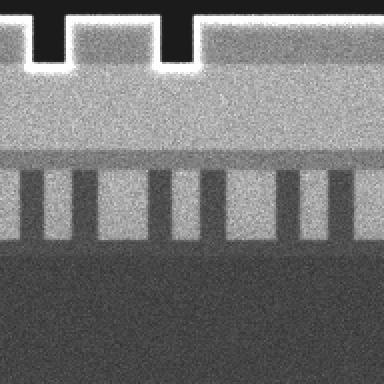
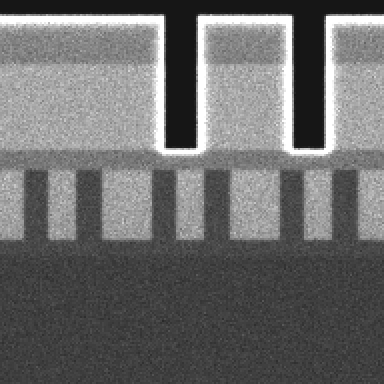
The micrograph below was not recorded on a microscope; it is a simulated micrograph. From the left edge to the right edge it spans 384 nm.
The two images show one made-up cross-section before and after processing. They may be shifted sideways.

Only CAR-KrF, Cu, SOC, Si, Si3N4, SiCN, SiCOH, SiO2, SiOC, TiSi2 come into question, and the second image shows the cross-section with SiO2 removed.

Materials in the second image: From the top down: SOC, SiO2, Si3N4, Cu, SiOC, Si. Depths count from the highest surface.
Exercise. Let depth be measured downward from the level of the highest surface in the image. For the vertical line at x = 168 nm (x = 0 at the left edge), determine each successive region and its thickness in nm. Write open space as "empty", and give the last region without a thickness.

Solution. empty 134, Si3N4 20, SiOC 86, Si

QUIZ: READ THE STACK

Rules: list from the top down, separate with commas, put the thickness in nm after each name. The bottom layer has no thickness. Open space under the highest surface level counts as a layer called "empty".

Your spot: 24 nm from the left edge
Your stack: SOC 48, SiO2 86, Si3N4 20, SiOC 86, Si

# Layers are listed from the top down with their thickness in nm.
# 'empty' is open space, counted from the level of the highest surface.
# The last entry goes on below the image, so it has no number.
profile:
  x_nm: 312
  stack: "empty 134, Si3N4 20, Cu 70, SiOC 16, Si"